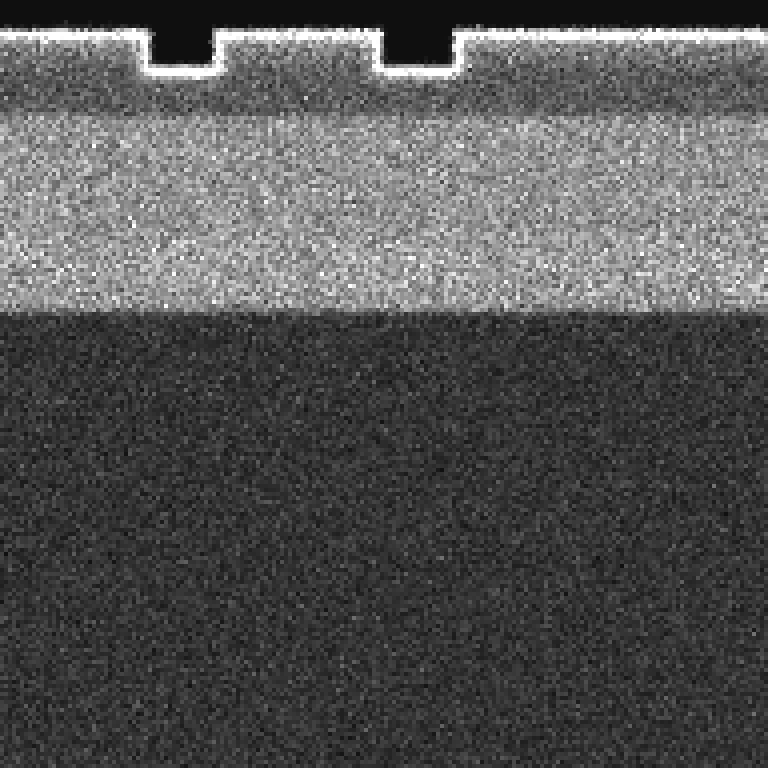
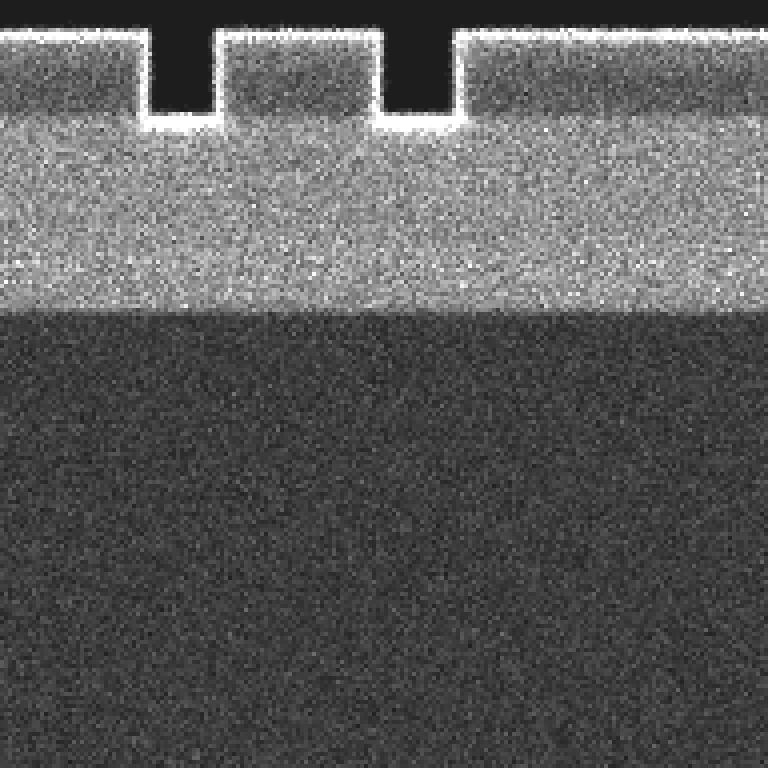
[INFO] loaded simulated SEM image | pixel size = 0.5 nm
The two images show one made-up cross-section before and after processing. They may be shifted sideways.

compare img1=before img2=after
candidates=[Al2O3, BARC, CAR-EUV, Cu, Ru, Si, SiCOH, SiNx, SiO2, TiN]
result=removed:SiNx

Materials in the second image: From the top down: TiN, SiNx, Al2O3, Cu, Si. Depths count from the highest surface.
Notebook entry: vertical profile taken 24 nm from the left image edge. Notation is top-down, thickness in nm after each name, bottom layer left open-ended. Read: TiN 18, SiNx 24, Al2O3 64, Cu 34, Si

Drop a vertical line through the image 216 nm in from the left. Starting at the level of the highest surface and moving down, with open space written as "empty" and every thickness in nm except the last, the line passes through empty 42, Al2O3 64, Cu 34, Si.